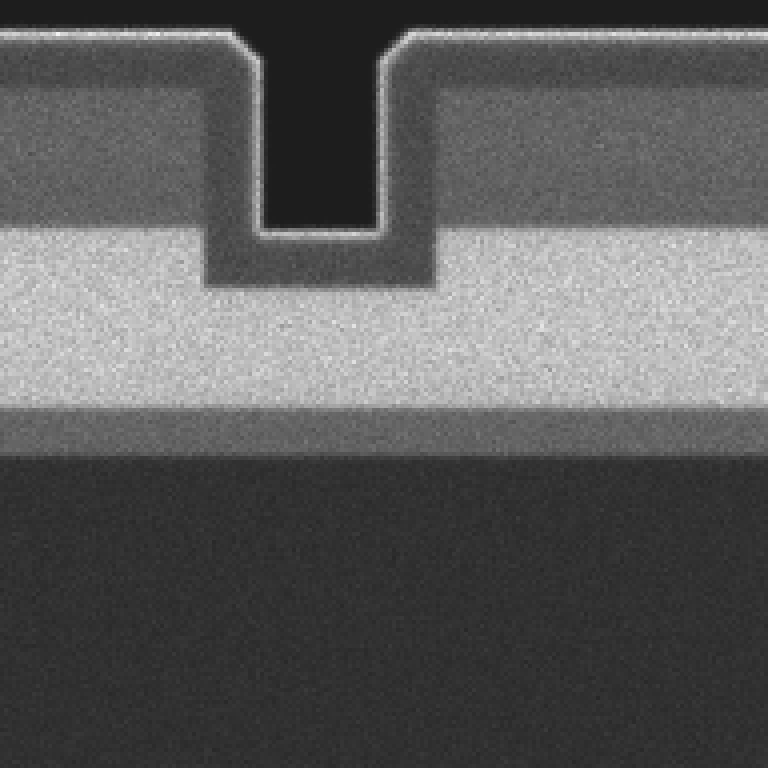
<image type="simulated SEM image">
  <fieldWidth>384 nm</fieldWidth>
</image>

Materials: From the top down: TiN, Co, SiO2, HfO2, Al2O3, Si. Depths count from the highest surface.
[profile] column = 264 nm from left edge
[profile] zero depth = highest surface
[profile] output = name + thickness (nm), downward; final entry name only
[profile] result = TiN 28, Co 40, SiO2 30, HfO2 90, Al2O3 24, Si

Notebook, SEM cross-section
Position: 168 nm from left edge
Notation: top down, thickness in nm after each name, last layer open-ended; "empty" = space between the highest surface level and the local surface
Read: empty 100, TiN 28, HfO2 60, Al2O3 24, Si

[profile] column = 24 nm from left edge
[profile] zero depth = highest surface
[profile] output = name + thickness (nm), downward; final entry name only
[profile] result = TiN 28, Co 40, SiO2 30, HfO2 90, Al2O3 24, Si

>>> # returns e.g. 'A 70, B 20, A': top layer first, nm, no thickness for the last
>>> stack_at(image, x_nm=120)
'empty 6, TiN 122, HfO2 60, Al2O3 24, Si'